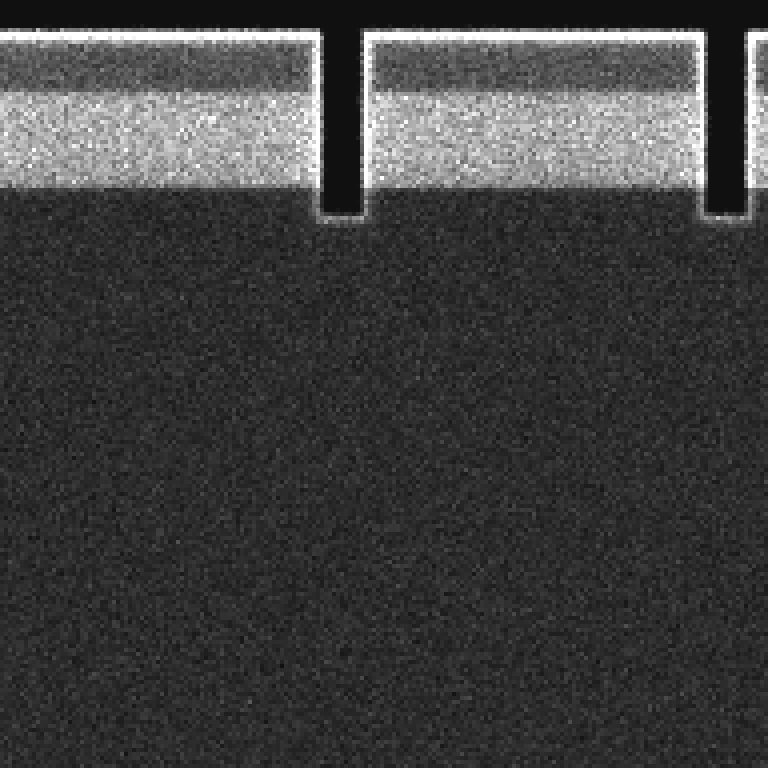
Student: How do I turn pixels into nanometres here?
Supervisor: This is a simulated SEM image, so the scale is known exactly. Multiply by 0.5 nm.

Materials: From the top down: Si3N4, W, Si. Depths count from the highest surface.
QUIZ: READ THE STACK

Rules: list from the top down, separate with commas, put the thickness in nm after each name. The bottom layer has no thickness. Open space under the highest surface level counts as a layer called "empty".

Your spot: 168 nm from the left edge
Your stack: empty 92, Si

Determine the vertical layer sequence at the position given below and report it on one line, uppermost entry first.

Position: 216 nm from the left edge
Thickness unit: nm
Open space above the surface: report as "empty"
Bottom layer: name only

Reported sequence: Si3N4 30, W 48, Si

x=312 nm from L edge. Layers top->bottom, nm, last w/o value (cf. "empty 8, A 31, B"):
Si3N4 30, W 48, Si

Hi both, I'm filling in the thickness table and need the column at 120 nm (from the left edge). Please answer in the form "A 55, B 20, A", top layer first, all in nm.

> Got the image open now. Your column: Si3N4 30, W 48, Si